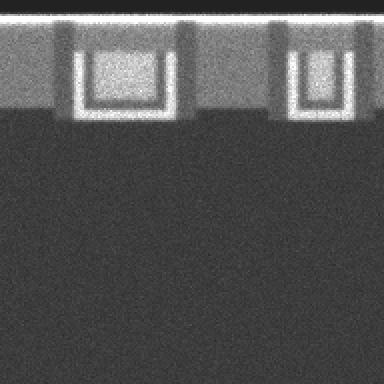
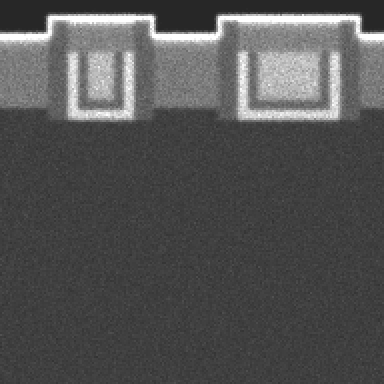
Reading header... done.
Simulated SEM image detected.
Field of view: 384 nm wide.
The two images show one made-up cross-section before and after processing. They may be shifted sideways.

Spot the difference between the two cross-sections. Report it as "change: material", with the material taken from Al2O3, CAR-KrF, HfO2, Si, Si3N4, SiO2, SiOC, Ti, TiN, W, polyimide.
removed: SiO2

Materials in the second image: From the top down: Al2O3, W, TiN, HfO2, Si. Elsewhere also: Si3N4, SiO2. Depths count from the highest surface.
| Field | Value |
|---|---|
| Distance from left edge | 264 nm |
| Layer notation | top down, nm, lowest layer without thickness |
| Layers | Al2O3 36, W 48, TiN 10, HfO2 10, Si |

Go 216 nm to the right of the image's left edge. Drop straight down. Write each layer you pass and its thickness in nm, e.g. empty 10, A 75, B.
empty 18, SiO2 74, Si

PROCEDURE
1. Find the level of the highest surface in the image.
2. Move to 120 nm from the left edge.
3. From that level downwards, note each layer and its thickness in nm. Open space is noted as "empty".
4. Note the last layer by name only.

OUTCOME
Al2O3 36, TiN 58, HfO2 10, Si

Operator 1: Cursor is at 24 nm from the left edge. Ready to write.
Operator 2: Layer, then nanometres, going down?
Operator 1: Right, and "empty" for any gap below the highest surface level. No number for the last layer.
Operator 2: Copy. empty 18, SiO2 74, Si